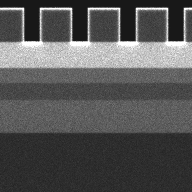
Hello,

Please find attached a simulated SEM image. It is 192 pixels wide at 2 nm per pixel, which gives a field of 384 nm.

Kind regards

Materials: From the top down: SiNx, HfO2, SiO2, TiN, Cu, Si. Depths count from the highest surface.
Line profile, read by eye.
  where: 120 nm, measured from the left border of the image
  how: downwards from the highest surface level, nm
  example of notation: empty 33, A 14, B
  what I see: SiNx 68, HfO2 52, SiO2 30, TiN 34, Cu 66, Si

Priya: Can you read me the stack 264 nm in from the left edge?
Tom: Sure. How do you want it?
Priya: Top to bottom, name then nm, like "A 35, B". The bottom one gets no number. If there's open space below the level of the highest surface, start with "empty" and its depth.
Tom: empty 68, HfO2 52, SiO2 30, TiN 34, Cu 66, Si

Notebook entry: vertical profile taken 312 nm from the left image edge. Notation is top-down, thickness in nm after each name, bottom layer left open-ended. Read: SiNx 68, HfO2 52, SiO2 30, TiN 34, Cu 66, Si